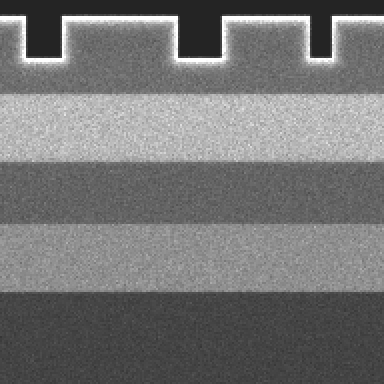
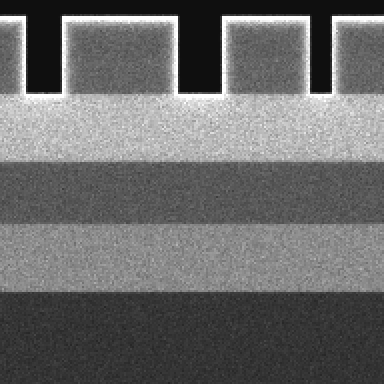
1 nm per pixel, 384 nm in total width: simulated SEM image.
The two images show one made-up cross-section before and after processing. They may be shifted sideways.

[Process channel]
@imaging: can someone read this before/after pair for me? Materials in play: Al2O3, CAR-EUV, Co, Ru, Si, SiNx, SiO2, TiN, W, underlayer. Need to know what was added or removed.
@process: underlayer removed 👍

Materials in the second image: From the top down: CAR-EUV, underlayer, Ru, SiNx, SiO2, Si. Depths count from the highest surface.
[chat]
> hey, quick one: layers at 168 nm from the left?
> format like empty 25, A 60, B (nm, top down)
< CAR-EUV 42, underlayer 36, Ru 68, SiNx 62, SiO2 68, Si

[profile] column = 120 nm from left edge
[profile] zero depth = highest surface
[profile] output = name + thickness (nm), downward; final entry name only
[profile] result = CAR-EUV 42, underlayer 36, Ru 68, SiNx 62, SiO2 68, Si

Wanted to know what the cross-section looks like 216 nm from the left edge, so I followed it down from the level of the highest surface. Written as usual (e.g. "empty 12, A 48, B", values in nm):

empty 78, Ru 68, SiNx 62, SiO2 68, Si